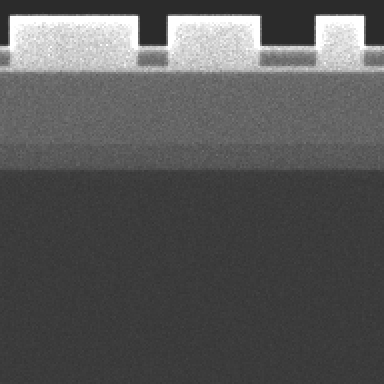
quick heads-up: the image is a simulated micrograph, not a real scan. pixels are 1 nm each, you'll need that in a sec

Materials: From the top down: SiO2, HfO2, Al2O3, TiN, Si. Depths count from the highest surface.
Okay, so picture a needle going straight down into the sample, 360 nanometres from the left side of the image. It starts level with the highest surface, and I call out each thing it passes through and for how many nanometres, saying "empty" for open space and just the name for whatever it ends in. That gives HfO2 56, Al2O3 72, TiN 26, Si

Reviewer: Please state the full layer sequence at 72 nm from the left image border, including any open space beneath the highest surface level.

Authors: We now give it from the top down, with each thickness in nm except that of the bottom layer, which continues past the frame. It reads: HfO2 56, Al2O3 72, TiN 26, Si